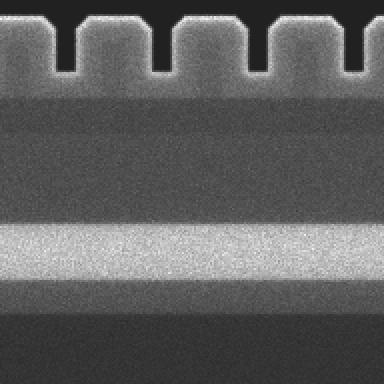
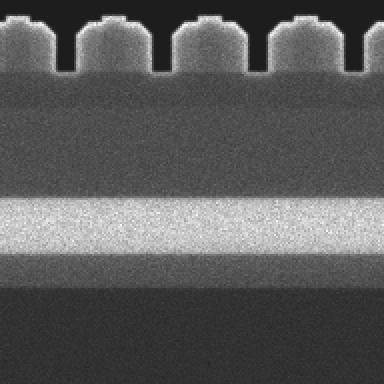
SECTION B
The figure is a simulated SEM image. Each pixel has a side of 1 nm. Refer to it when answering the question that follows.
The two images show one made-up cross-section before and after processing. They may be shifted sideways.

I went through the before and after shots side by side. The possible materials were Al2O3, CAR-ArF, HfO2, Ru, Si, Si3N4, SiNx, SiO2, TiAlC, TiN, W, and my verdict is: removed, Al2O3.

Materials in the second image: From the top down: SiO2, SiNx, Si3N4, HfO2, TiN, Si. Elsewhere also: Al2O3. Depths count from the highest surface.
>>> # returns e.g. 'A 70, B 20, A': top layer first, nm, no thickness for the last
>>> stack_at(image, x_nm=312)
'SiO2 56, SiNx 36, Si3N4 90, HfO2 56, TiN 34, Si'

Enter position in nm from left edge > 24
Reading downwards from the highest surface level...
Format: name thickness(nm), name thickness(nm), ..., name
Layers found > SiO2 56, SiNx 36, Si3N4 90, HfO2 56, TiN 34, Si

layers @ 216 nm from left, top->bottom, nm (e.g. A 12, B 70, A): SiO2 56, SiNx 36, Si3N4 90, HfO2 56, TiN 34, Si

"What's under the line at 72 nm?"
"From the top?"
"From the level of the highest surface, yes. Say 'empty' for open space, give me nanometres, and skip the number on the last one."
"empty 56, SiNx 36, Si3N4 90, HfO2 56, TiN 34, Si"